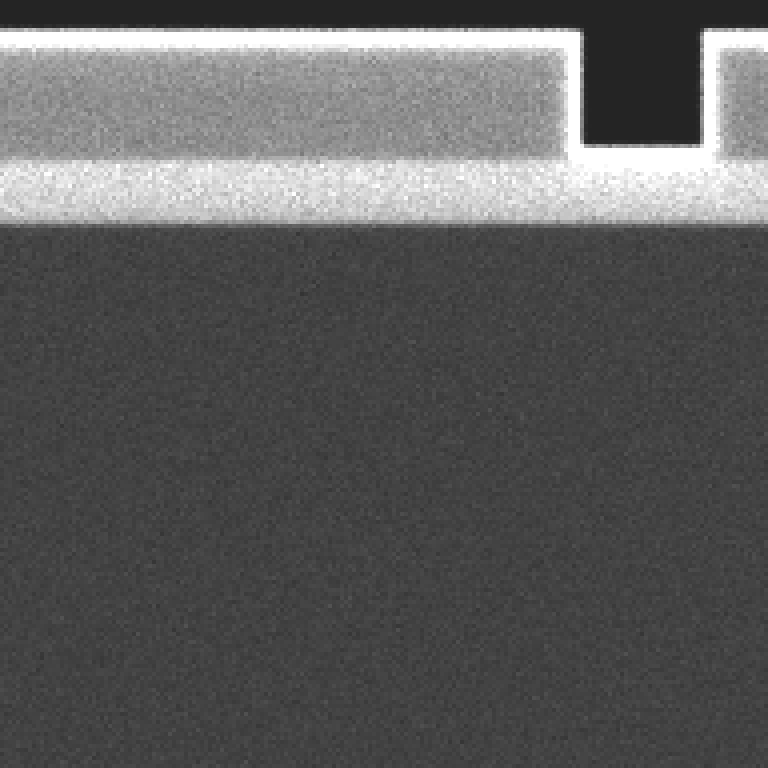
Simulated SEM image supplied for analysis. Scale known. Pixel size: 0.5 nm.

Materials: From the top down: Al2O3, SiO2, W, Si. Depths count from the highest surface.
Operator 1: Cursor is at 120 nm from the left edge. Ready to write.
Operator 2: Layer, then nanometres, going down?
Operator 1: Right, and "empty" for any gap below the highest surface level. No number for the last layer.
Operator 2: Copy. Al2O3 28, SiO2 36, W 32, Si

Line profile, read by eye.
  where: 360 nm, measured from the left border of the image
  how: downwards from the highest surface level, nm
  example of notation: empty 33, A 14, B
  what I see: Al2O3 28, SiO2 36, W 32, Si